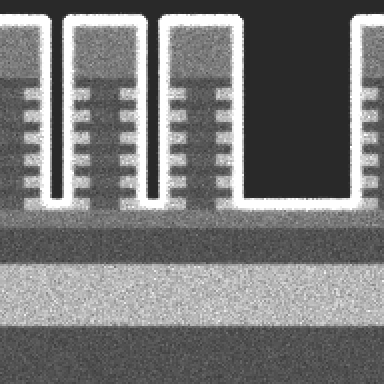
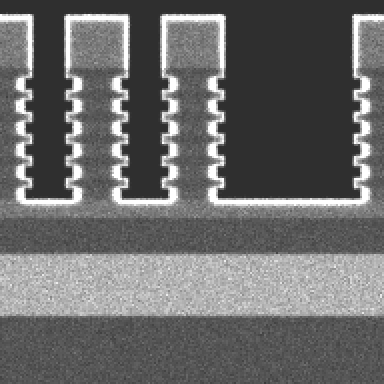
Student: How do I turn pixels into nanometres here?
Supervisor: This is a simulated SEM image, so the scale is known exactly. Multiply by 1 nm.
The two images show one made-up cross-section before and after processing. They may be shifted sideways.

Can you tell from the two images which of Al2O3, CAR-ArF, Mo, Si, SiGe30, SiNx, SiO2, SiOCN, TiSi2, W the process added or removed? Yes, it removed Al2O3.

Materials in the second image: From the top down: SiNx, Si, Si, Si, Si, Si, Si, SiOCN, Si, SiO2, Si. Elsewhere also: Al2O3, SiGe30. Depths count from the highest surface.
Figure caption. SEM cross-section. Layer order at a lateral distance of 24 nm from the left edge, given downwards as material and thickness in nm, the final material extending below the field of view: SiNx 52, Si 10, empty 12, Si 10, empty 12, Si 10, empty 12, Si 10, empty 12, Si 10, empty 12, Si 10, empty 12, SiOCN 18, Si 36, SiO2 62, Si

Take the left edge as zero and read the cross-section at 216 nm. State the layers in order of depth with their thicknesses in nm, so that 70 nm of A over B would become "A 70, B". SiNx 52, Si 10, empty 12, Si 10, empty 12, Si 10, empty 12, Si 10, empty 12, Si 10, empty 12, Si 10, empty 12, SiOCN 18, Si 36, SiO2 62, Si